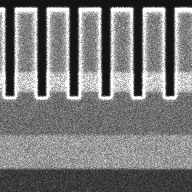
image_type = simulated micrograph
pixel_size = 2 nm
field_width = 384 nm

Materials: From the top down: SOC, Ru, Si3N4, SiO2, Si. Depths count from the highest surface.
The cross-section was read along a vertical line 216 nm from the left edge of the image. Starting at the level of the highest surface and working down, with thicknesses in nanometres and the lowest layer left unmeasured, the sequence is empty 178, Si3N4 76, SiO2 68, Si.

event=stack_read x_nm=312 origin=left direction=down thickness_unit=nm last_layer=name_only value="SOC 128, Ru 40, Si3N4 86, SiO2 68, Si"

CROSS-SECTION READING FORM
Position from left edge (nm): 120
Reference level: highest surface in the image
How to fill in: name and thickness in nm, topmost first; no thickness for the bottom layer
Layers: SOC 128, Ru 40, Si3N4 86, SiO2 68, Si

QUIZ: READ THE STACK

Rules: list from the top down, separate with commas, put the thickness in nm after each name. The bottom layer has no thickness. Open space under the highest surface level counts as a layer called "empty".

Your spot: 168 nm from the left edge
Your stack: SOC 128, Ru 40, Si3N4 86, SiO2 68, Si